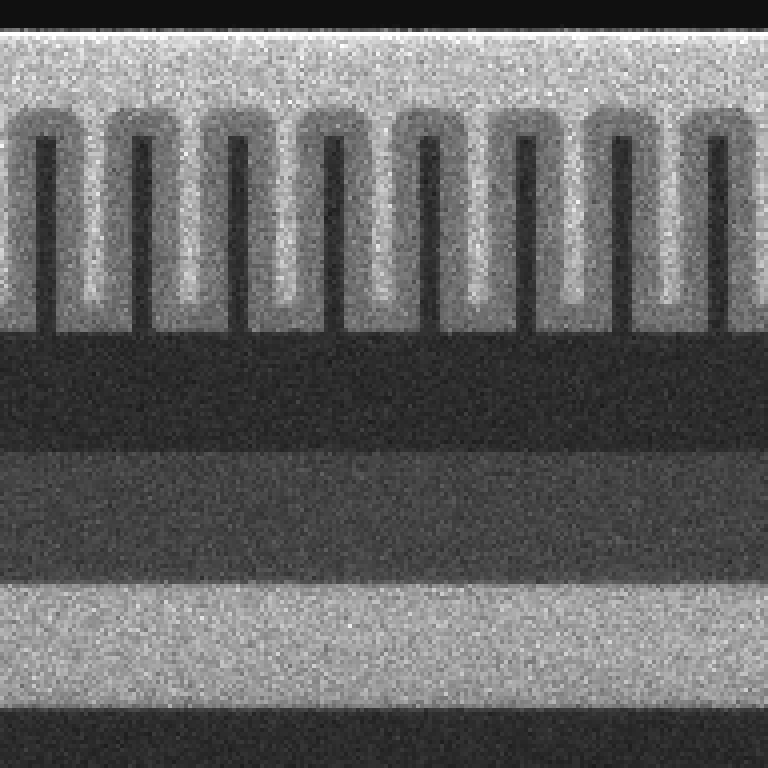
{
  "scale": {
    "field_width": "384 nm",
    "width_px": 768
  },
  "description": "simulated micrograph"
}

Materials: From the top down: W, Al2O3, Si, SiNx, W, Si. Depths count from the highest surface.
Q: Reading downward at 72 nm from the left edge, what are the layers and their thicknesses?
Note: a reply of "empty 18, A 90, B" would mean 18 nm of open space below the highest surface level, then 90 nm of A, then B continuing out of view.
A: W 38, Al2O3 14, Si 158, SiNx 66, W 62, Si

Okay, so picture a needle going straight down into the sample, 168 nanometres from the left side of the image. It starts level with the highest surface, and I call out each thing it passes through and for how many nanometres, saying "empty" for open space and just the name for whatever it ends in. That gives W 38, Al2O3 14, Si 158, SiNx 66, W 62, Si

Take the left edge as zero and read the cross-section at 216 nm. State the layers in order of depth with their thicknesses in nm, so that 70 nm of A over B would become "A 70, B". W 38, Al2O3 14, Si 158, SiNx 66, W 62, Si